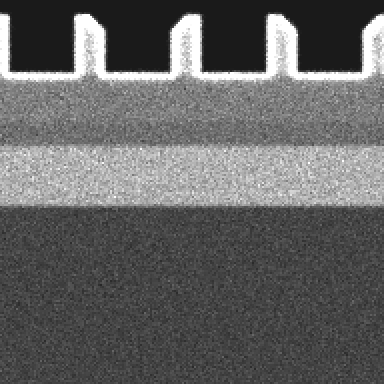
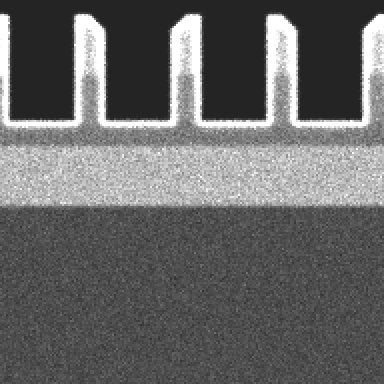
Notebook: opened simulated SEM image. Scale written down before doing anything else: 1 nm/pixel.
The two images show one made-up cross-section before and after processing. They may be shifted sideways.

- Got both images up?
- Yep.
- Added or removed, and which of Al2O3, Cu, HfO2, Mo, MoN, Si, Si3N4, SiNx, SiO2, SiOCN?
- removed, Si3N4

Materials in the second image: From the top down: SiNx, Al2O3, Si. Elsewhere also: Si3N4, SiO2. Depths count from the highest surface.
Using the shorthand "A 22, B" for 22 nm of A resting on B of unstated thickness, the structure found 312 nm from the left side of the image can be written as empty 106, SiNx 24, Al2O3 60, Si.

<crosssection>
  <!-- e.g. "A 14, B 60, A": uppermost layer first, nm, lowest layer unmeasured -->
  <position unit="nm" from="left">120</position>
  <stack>empty 106, SiNx 24, Al2O3 60, Si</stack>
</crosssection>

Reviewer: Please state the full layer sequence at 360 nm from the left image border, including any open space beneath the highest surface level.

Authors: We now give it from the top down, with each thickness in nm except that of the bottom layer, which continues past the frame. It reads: empty 106, SiNx 24, Al2O3 60, Si